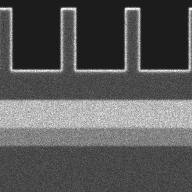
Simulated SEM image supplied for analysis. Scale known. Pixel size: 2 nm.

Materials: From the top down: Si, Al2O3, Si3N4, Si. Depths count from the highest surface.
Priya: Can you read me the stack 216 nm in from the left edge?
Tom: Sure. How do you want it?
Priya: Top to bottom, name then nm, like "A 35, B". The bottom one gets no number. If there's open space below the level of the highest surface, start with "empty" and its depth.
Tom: empty 124, Si 60, Al2O3 56, Si3N4 36, Si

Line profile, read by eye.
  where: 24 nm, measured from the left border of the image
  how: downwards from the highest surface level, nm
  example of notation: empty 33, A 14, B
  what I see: empty 124, Si 60, Al2O3 56, Si3N4 36, Si